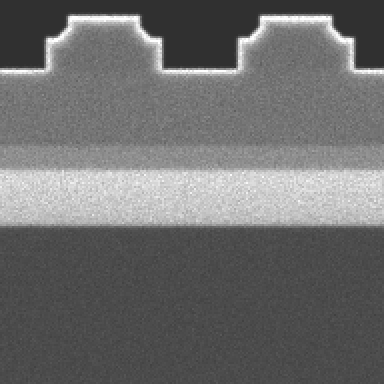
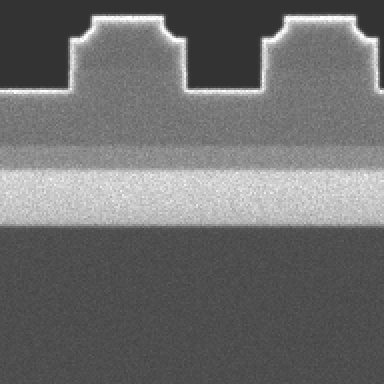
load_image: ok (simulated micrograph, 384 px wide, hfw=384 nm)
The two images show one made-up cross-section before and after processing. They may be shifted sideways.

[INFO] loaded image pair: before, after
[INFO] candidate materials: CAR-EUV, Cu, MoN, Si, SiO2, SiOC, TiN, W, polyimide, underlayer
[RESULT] removed TiN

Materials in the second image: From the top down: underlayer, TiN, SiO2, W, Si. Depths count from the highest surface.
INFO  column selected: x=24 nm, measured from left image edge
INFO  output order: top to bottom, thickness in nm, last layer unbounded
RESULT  empty 74, TiN 56, SiO2 24, W 56, Si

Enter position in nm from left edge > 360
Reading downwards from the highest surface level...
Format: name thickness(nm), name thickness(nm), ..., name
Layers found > empty 16, underlayer 38, TiN 76, SiO2 24, W 56, Si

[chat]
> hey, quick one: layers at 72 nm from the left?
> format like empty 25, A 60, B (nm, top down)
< empty 22, underlayer 32, TiN 76, SiO2 24, W 56, Si